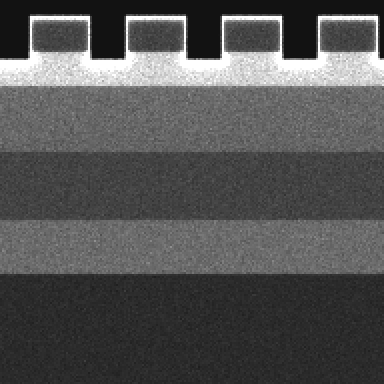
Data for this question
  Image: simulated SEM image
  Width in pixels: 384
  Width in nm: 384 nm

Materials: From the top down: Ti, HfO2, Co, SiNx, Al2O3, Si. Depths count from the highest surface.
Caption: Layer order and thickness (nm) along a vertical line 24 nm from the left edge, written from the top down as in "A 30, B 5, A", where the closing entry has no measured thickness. empty 44, HfO2 26, Co 66, SiNx 68, Al2O3 54, Si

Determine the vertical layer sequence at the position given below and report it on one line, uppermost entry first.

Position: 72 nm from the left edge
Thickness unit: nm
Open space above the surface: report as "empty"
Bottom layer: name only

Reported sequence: Ti 36, HfO2 34, Co 66, SiNx 68, Al2O3 54, Si